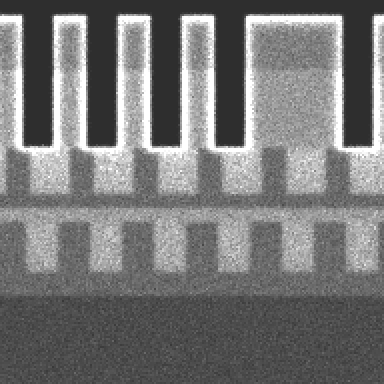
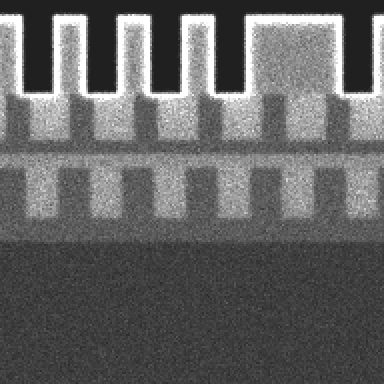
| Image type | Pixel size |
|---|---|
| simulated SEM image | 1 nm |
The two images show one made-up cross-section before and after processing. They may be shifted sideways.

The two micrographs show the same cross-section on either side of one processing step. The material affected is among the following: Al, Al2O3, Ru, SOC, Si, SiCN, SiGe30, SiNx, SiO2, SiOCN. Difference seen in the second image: SOC removed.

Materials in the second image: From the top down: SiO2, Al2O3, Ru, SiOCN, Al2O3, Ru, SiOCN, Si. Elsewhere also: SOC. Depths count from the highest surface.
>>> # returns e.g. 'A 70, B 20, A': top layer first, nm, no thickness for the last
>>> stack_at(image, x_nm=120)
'SiO2 70, Al2O3 8, Ru 46, SiOCN 14, Al2O3 14, Ru 50, SiOCN 24, Si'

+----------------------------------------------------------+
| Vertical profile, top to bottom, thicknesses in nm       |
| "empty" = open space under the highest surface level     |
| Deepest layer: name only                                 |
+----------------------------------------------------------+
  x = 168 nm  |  empty 78, Ru 46, SiOCN 14, Al2O3 14, Ru 50, SiOCN 24, Si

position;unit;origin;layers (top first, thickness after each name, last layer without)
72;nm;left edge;SiO2 70, Al2O3 8, SiOCN 60, Al2O3 14, SiOCN 74, Si